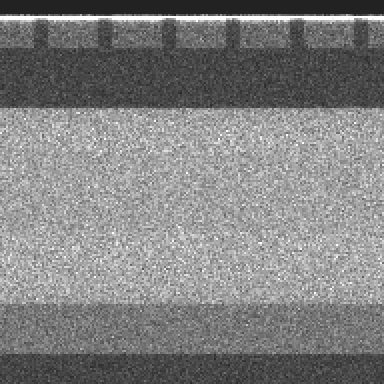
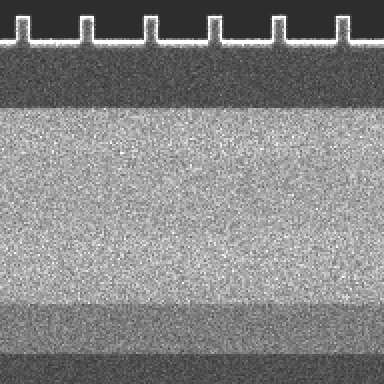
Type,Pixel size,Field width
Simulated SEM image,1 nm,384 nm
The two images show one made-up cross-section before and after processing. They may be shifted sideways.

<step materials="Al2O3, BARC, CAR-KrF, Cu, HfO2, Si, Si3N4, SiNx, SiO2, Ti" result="removed SiNx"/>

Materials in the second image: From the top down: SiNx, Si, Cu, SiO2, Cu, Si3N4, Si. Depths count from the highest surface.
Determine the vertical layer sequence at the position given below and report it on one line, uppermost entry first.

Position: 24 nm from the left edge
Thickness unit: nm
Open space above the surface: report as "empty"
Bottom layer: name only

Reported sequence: Si 92, Cu 46, SiO2 78, Cu 72, Si3N4 50, Si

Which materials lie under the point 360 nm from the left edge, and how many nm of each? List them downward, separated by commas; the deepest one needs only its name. empty 24, SiNx 8, Si 60, Cu 46, SiO2 78, Cu 72, Si3N4 50, Si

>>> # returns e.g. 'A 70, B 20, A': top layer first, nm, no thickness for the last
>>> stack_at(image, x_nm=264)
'empty 24, SiNx 8, Si 60, Cu 46, SiO2 78, Cu 72, Si3N4 50, Si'